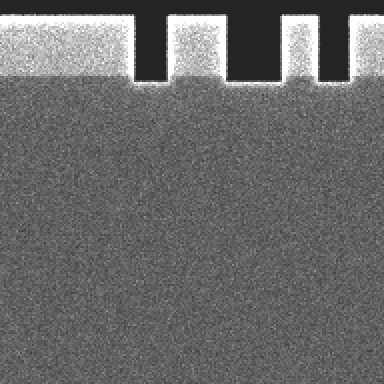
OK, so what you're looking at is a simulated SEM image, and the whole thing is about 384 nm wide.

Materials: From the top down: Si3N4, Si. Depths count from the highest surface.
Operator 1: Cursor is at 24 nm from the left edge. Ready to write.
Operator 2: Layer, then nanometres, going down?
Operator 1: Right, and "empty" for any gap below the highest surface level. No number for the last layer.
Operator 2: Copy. Si3N4 60, Si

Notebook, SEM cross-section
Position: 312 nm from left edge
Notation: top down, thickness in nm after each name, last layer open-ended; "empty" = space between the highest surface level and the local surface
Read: Si3N4 60, Si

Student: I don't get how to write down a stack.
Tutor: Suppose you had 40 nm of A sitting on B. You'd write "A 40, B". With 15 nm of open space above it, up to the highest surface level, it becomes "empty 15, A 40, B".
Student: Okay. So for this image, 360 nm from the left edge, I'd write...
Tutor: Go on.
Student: Si3N4 60, Si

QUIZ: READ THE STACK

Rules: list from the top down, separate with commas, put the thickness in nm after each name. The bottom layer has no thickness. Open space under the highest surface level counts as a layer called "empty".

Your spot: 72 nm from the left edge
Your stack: Si3N4 60, Si